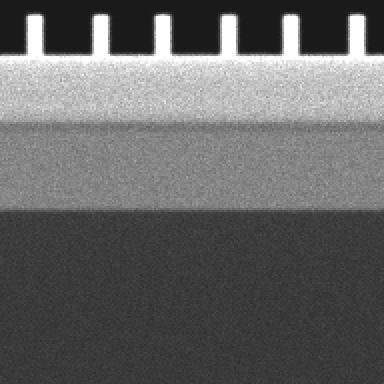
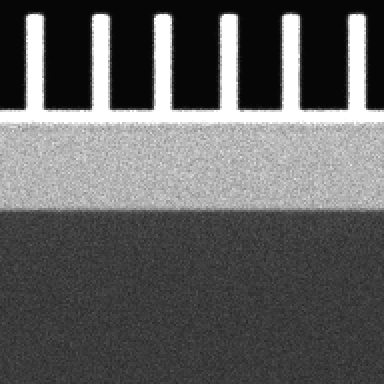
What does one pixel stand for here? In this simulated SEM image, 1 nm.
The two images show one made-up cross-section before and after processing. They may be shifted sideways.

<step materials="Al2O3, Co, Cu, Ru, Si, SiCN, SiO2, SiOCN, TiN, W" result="removed Ru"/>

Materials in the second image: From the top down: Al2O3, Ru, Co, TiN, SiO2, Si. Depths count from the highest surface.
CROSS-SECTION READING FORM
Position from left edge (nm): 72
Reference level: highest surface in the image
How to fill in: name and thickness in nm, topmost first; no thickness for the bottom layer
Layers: empty 96, Co 10, TiN 10, SiO2 78, Si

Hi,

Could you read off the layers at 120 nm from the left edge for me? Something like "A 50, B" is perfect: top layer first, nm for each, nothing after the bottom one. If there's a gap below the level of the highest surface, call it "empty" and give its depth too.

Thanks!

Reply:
empty 96, Co 10, TiN 10, SiO2 78, Si